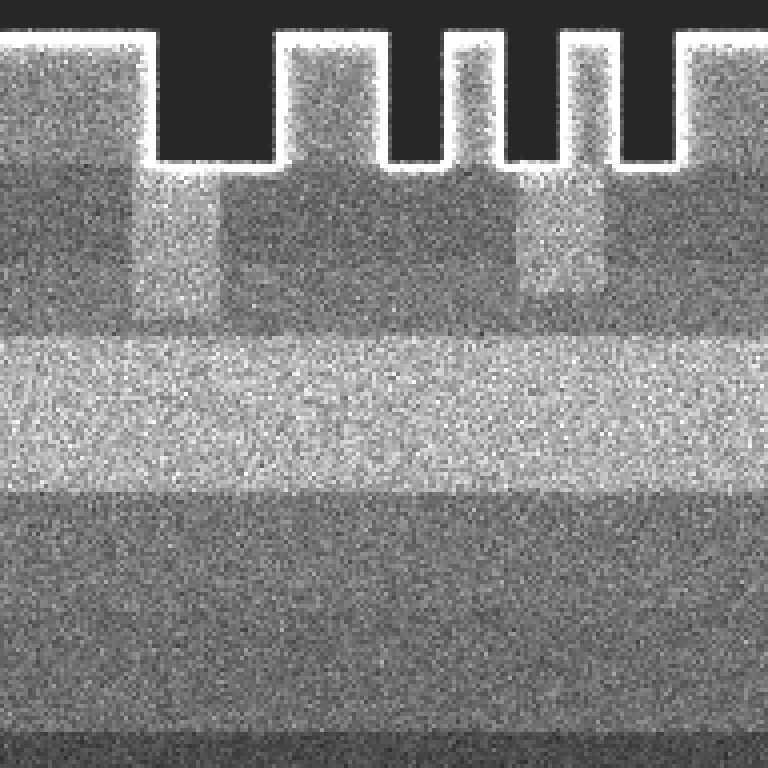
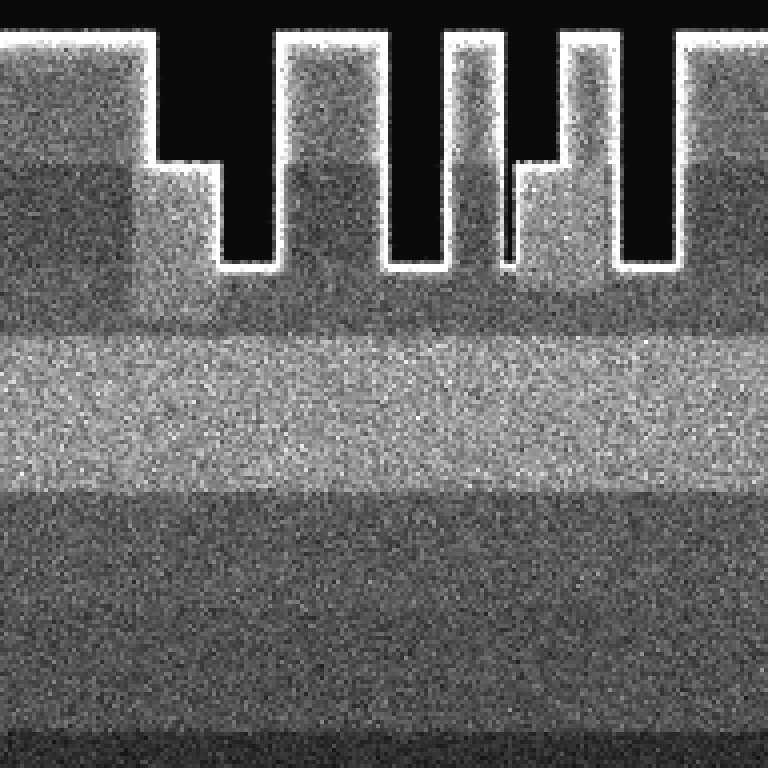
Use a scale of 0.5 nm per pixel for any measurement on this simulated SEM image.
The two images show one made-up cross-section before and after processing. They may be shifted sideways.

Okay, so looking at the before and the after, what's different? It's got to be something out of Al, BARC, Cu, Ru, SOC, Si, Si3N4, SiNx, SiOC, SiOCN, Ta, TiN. SiNx, removed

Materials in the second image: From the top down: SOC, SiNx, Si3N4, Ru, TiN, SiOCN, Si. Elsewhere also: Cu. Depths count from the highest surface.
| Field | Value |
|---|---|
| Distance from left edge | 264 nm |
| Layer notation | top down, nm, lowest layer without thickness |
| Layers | empty 66, Cu 64, Si3N4 22, Ru 78, TiN 58, SiOCN 62, Si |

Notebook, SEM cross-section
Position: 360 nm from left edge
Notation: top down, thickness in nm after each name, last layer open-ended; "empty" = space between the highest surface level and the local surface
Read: SOC 66, SiNx 50, Si3N4 36, Ru 78, TiN 58, SiOCN 62, Si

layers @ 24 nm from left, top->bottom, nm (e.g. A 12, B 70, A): SOC 66, SiNx 50, Si3N4 36, Ru 78, TiN 58, SiOCN 62, Si